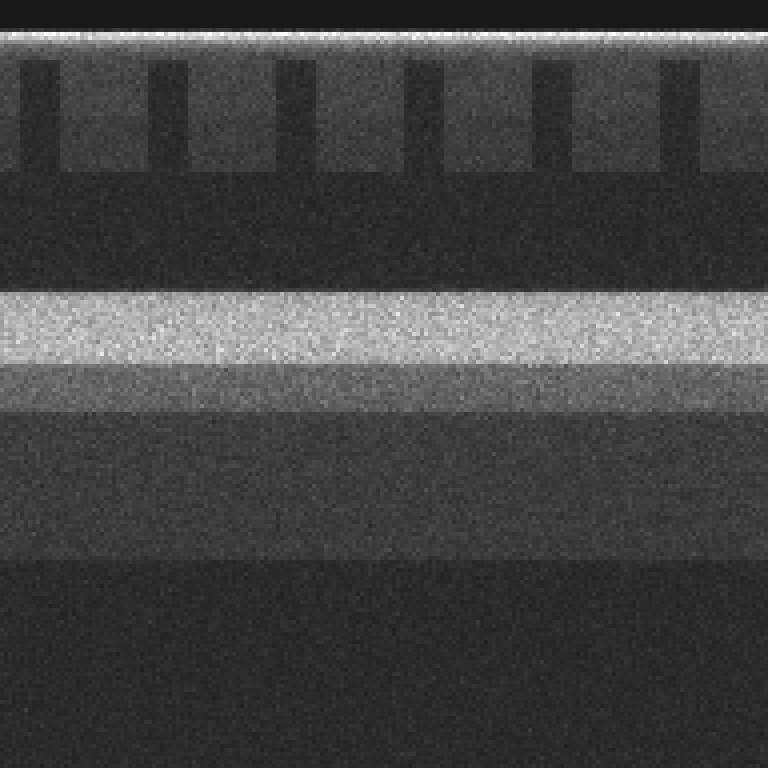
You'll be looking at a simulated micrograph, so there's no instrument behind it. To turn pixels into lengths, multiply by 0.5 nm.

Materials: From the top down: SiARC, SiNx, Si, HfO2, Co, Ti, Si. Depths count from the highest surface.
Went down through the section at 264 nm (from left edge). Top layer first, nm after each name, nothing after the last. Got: SiARC 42, SiNx 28, Si 60, HfO2 36, Co 24, Ti 74, Si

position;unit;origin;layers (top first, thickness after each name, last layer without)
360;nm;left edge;SiARC 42, SiNx 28, Si 60, HfO2 36, Co 24, Ti 74, Si